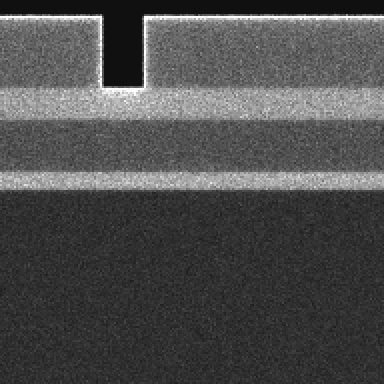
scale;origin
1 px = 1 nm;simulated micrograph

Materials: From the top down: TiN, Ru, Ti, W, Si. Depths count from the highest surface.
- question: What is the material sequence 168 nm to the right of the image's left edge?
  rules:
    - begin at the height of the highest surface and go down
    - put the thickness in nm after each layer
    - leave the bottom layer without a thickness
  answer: TiN 72, Ru 32, Ti 52, W 18, Si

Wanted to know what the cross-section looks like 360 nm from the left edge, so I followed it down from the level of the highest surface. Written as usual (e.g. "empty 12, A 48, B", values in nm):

TiN 72, Ru 32, Ti 52, W 18, Si